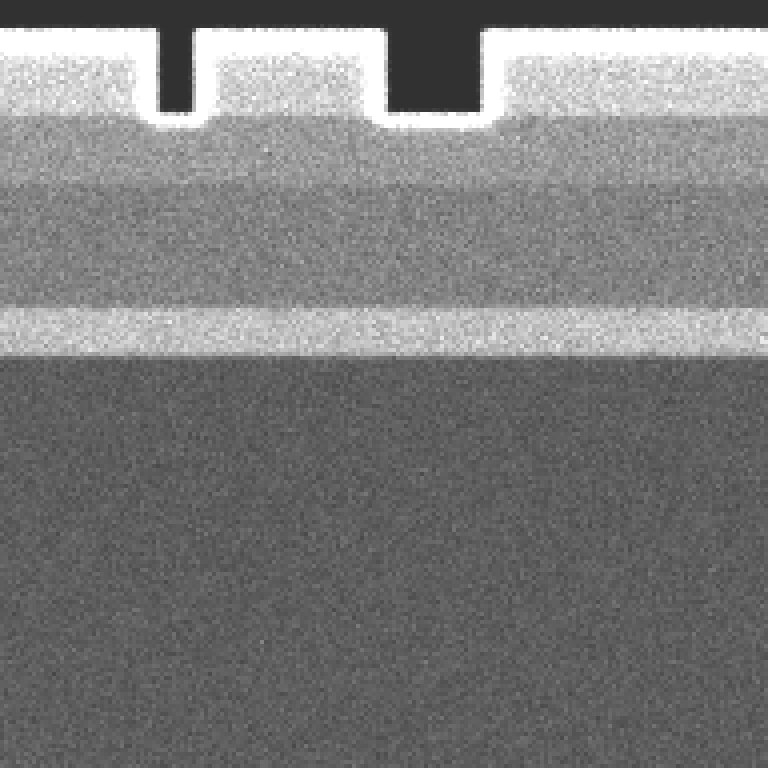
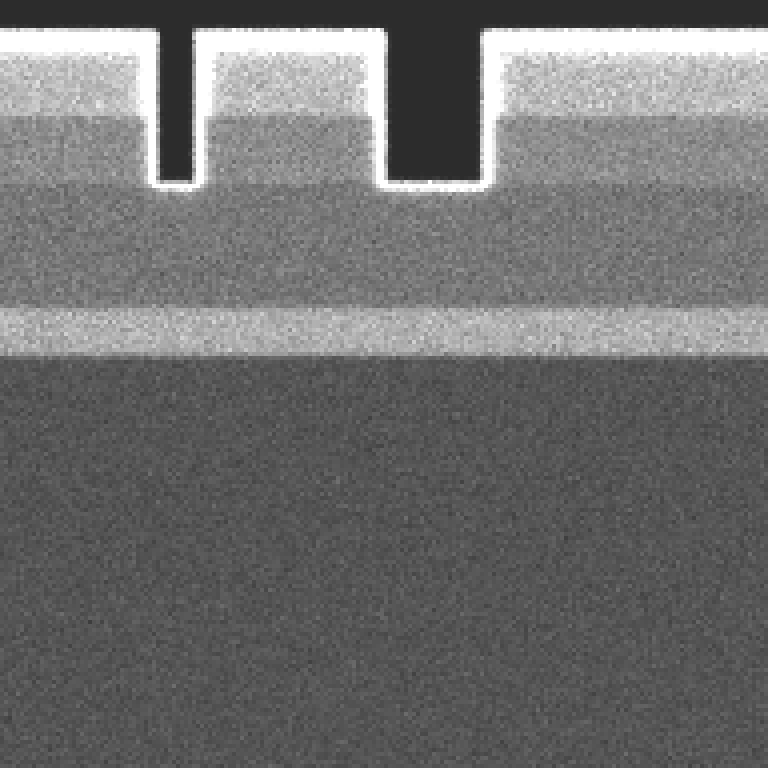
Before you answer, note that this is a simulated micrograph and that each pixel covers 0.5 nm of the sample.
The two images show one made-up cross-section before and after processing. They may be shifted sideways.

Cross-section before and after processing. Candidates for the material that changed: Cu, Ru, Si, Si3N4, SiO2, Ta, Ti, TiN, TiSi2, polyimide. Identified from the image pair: Si3N4 (removed).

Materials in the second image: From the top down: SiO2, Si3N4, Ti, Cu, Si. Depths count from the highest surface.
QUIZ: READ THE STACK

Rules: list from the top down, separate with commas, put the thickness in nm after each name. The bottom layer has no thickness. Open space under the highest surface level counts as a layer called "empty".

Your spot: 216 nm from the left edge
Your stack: empty 76, Ti 62, Cu 24, Si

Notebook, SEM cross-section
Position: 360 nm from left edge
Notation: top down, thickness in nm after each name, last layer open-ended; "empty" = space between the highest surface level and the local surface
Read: SiO2 42, Si3N4 34, Ti 62, Cu 24, Si